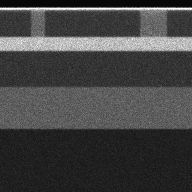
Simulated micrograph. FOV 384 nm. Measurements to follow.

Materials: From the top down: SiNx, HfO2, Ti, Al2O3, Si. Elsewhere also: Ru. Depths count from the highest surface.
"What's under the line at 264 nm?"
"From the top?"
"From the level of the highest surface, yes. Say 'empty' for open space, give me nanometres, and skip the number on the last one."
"SiNx 58, HfO2 28, Ti 72, Al2O3 84, Si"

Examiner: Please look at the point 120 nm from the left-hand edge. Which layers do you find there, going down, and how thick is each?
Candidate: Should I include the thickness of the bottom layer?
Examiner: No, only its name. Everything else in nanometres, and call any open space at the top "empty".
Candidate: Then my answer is SiNx 58, HfO2 28, Ti 72, Al2O3 84, Si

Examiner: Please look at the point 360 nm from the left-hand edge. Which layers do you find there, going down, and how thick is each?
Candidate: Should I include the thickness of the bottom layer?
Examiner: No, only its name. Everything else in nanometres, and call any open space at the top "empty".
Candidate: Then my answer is SiNx 58, HfO2 28, Ti 72, Al2O3 84, Si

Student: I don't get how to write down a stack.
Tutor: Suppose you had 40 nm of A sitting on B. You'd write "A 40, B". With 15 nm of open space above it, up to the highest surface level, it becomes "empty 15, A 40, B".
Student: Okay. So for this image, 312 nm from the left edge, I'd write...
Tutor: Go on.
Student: Ru 58, HfO2 28, Ti 72, Al2O3 84, Si